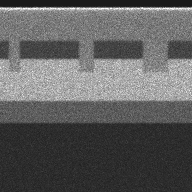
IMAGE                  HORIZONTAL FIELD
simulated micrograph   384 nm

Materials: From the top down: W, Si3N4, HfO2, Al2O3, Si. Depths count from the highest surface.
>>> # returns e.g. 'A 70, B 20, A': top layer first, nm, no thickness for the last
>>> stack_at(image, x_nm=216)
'W 66, Si3N4 36, HfO2 84, Al2O3 44, Si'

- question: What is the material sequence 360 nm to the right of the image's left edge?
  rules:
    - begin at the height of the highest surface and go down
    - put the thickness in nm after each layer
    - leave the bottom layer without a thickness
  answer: W 66, Si3N4 36, HfO2 84, Al2O3 44, Si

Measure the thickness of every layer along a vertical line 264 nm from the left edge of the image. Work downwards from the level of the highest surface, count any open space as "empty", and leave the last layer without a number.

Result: W 66, Si3N4 36, HfO2 84, Al2O3 44, Si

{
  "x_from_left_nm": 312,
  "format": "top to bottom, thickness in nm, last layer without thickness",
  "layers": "W 128, HfO2 58, Al2O3 44, Si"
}